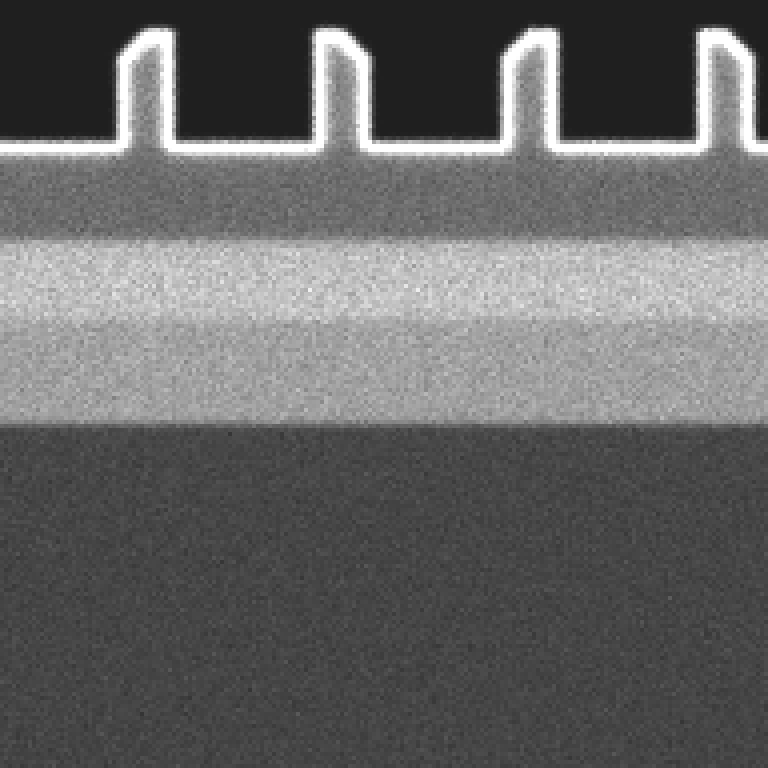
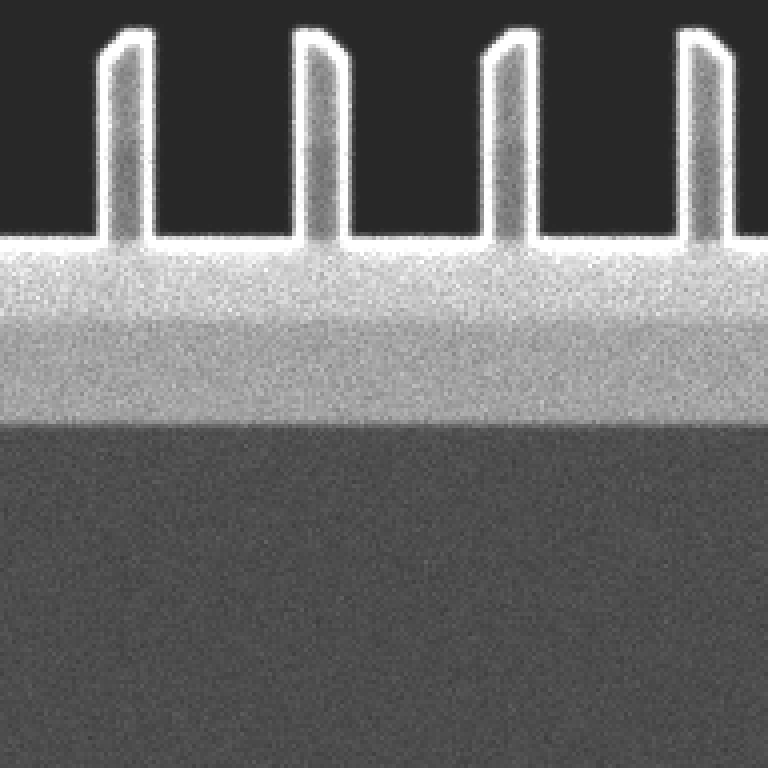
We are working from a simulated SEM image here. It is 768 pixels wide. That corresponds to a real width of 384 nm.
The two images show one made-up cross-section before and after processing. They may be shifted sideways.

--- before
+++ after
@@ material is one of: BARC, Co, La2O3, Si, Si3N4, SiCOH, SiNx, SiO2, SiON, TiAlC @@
SiNx removed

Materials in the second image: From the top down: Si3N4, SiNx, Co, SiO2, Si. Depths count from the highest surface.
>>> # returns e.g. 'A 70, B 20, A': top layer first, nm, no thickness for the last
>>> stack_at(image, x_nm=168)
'empty 8, Si3N4 48, SiNx 48, Co 40, SiO2 52, Si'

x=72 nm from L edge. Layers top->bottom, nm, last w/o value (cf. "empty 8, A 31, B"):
Si3N4 56, SiNx 48, Co 40, SiO2 52, Si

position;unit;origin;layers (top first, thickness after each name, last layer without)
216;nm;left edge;empty 104, Co 40, SiO2 52, Si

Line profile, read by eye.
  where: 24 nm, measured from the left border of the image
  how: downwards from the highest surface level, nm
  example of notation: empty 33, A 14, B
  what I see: empty 104, Co 40, SiO2 52, Si